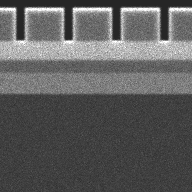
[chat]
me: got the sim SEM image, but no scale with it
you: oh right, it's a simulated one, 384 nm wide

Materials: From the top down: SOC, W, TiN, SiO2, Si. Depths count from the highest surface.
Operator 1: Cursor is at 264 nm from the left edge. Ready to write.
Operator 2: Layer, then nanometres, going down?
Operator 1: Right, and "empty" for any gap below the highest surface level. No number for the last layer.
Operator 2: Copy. SOC 66, W 38, TiN 26, SiO2 42, Si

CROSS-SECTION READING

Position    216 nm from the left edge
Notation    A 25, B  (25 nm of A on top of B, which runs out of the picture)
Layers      SOC 66, W 38, TiN 26, SiO2 42, Si